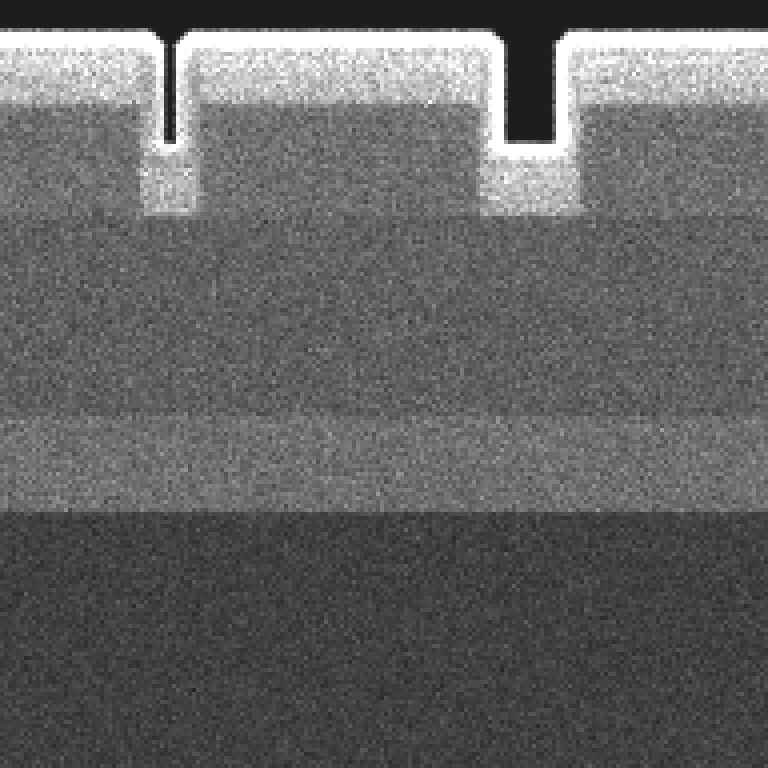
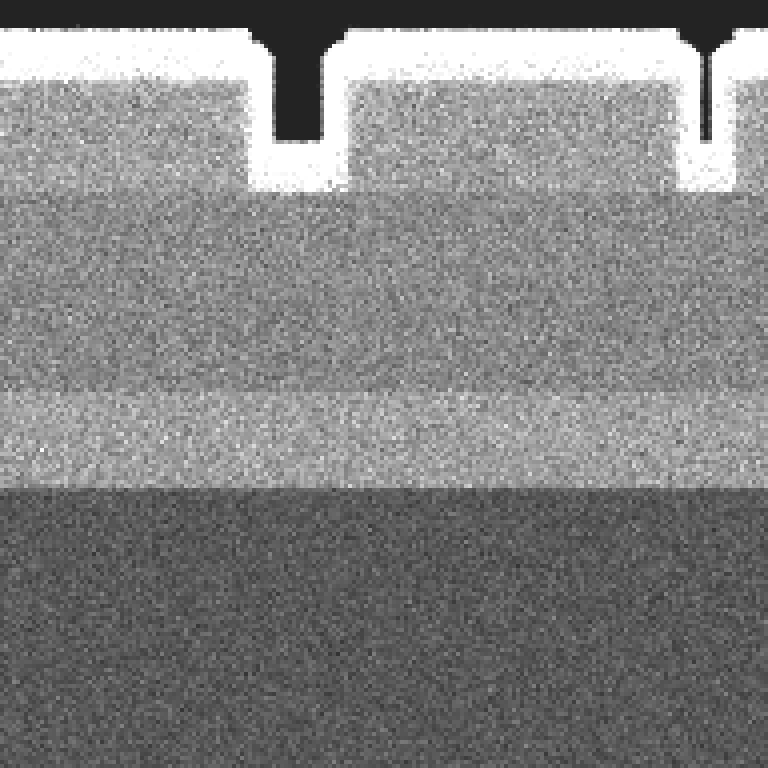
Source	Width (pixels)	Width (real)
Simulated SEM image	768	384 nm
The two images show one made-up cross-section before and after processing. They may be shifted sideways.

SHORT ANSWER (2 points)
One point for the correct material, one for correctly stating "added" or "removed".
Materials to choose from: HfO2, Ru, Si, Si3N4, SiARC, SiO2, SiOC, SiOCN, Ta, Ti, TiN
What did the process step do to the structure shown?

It removed SiO2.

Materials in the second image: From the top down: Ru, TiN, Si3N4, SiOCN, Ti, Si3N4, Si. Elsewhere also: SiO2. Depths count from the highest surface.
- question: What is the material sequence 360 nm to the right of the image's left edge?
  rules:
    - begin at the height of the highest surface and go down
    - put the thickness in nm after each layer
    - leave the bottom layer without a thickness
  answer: empty 8, SiO2 48, Ru 24, SiOCN 46, Ti 54, Si3N4 48, Si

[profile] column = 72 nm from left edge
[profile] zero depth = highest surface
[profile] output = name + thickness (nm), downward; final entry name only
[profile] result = Ru 24, TiN 30, Si3N4 26, SiOCN 46, Ti 54, Si3N4 48, Si